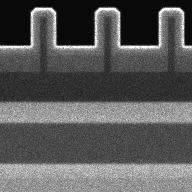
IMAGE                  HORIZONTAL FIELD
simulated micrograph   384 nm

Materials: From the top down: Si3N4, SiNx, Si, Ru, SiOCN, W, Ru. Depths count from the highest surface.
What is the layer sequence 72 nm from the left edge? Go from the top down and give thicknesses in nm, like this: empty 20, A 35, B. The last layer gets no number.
Si3N4 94, SiNx 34, Si 60, Ru 42, SiOCN 82, W 28, Ru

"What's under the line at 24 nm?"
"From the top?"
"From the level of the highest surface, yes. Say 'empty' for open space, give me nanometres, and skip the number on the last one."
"empty 76, Si3N4 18, SiNx 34, Si 60, Ru 42, SiOCN 82, W 28, Ru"